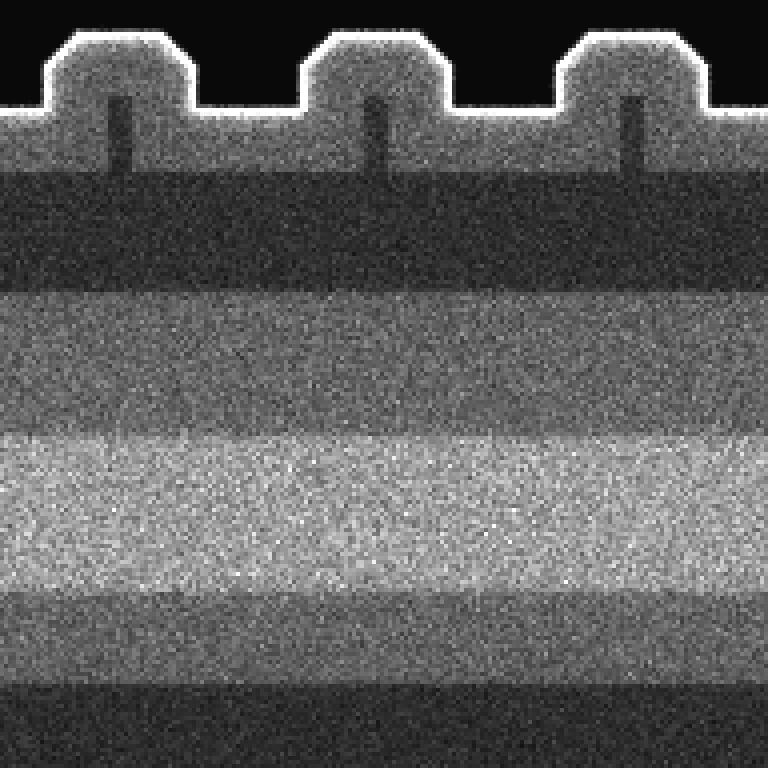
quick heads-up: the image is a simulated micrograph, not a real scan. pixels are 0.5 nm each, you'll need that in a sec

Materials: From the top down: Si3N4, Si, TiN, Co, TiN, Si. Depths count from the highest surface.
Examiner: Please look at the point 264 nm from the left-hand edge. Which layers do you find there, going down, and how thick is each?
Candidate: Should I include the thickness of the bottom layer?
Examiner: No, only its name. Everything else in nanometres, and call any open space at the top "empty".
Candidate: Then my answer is empty 38, Si3N4 32, Si 60, TiN 72, Co 78, TiN 46, Si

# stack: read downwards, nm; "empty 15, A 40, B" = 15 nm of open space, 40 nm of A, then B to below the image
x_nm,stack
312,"Si3N4 32, Si 98, TiN 72, Co 78, TiN 46, Si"